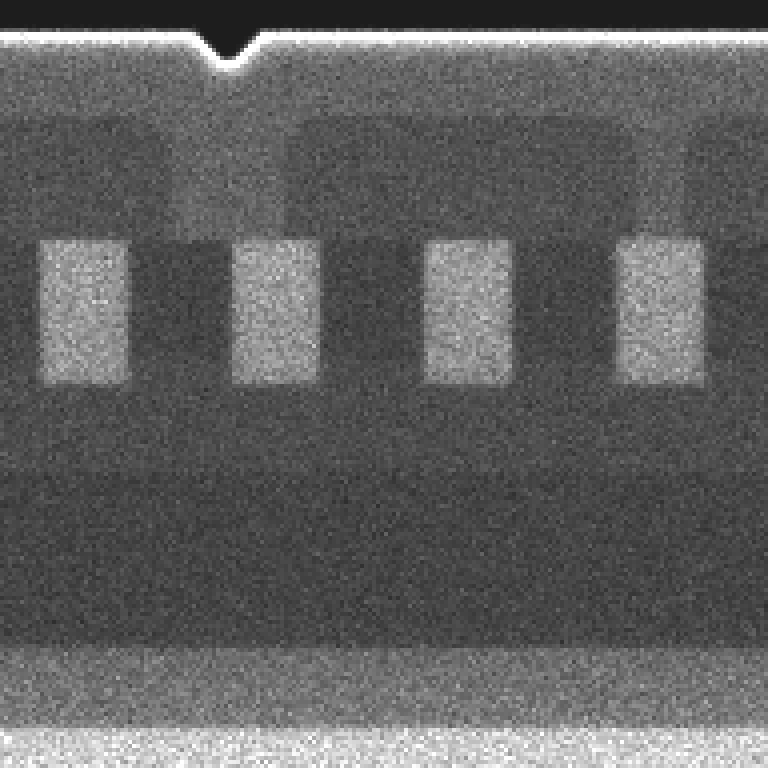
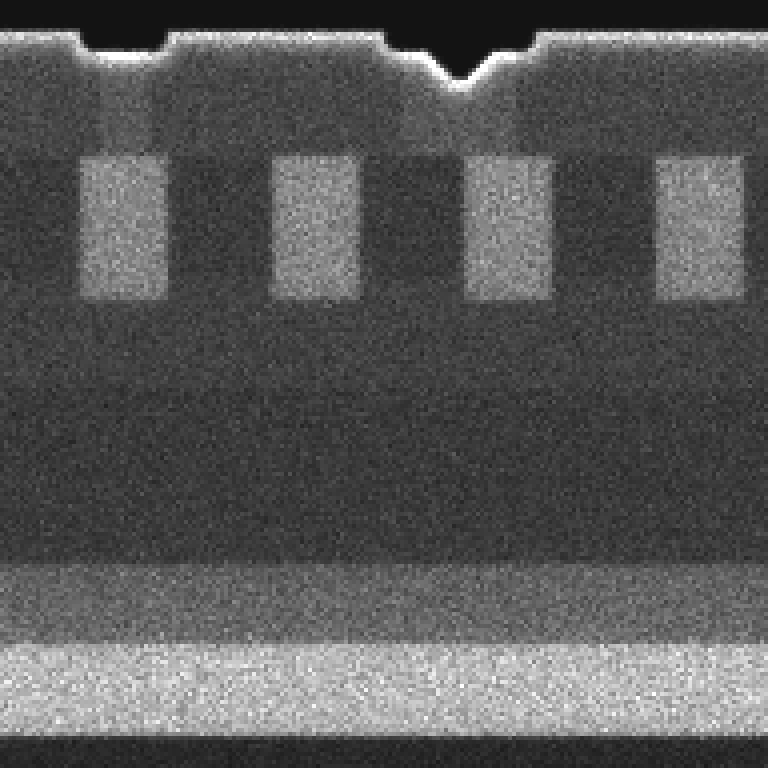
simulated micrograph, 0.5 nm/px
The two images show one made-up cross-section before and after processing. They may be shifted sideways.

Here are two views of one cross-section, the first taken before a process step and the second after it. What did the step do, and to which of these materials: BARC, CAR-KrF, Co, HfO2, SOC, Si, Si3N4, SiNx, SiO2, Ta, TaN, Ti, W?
It removed SiO2.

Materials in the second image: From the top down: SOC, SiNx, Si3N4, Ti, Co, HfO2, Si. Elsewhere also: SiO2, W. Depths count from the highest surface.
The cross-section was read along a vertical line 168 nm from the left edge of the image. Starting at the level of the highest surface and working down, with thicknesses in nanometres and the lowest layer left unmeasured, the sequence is SOC 62, W 72, Si3N4 44, Ti 88, Co 40, HfO2 46, Si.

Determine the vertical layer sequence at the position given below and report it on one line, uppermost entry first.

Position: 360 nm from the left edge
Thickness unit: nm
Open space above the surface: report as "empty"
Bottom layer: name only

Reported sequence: SOC 62, W 72, Si3N4 44, Ti 88, Co 40, HfO2 46, Si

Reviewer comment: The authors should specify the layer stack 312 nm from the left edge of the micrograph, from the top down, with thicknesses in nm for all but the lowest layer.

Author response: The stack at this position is SOC 62, SiNx 60, Si3N4 56, Ti 88, Co 40, HfO2 46, Si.